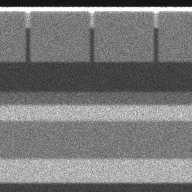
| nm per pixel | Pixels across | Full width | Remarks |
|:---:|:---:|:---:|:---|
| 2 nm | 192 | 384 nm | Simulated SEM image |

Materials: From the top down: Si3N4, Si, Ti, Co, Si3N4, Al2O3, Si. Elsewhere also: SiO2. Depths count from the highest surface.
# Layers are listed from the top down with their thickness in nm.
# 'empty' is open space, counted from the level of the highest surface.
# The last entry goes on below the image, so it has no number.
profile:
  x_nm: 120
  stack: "Si3N4 108, Si 60, Ti 26, Co 32, Si3N4 76, Al2O3 48, Si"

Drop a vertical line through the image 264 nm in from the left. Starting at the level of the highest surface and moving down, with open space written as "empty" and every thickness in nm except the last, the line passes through Si3N4 108, Si 60, Ti 26, Co 32, Si3N4 76, Al2O3 48, Si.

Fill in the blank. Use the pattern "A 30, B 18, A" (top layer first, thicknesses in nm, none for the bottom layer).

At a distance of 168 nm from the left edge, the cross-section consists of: Si3N4 108, Si 60, Ti 26, Co 32, Si3N4 76, Al2O3 48, Si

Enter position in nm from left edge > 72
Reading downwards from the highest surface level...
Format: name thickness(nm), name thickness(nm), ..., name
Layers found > Si3N4 108, Si 60, Ti 26, Co 32, Si3N4 76, Al2O3 48, Si